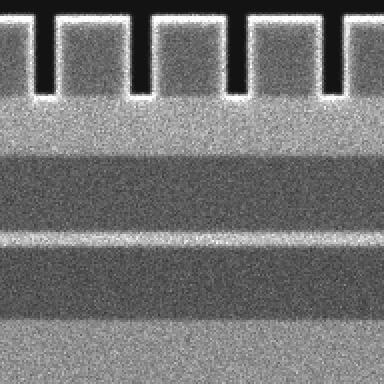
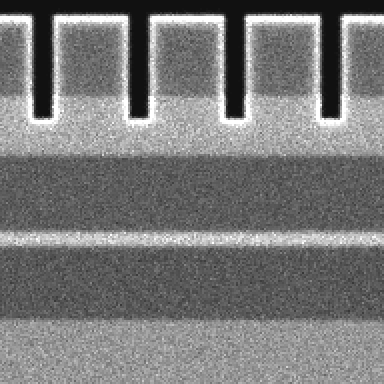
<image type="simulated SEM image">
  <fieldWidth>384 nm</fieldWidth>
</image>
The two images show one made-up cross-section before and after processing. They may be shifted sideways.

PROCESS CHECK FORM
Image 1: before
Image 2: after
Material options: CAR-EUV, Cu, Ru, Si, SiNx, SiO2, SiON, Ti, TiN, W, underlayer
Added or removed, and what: removed, Ru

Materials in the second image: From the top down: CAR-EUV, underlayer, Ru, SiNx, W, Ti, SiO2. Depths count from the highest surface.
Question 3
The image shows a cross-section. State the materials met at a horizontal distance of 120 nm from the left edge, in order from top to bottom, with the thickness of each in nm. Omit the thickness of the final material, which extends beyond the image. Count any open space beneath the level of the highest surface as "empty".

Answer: CAR-EUV 60, underlayer 20, Ru 60, SiNx 76, W 14, Ti 74, SiO2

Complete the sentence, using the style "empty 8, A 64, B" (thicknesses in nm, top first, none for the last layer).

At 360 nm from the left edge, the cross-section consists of CAR-EUV 60, underlayer 20, Ru 60, SiNx 76, W 14, Ti 74, SiO2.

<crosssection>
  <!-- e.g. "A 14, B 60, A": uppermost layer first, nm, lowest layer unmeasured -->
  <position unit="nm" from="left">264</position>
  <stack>CAR-EUV 60, underlayer 20, Ru 60, SiNx 76, W 14, Ti 74, SiO2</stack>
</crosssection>